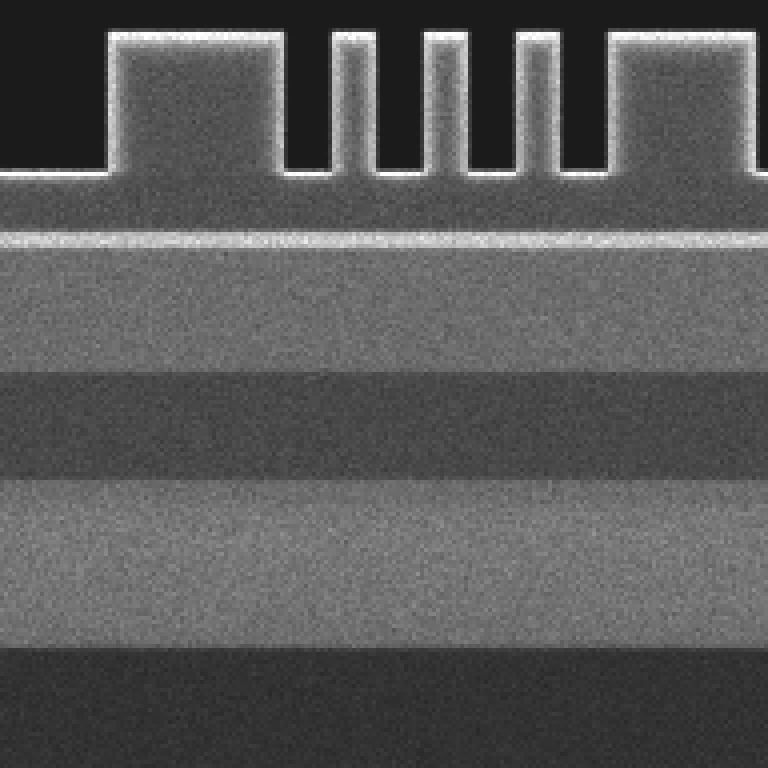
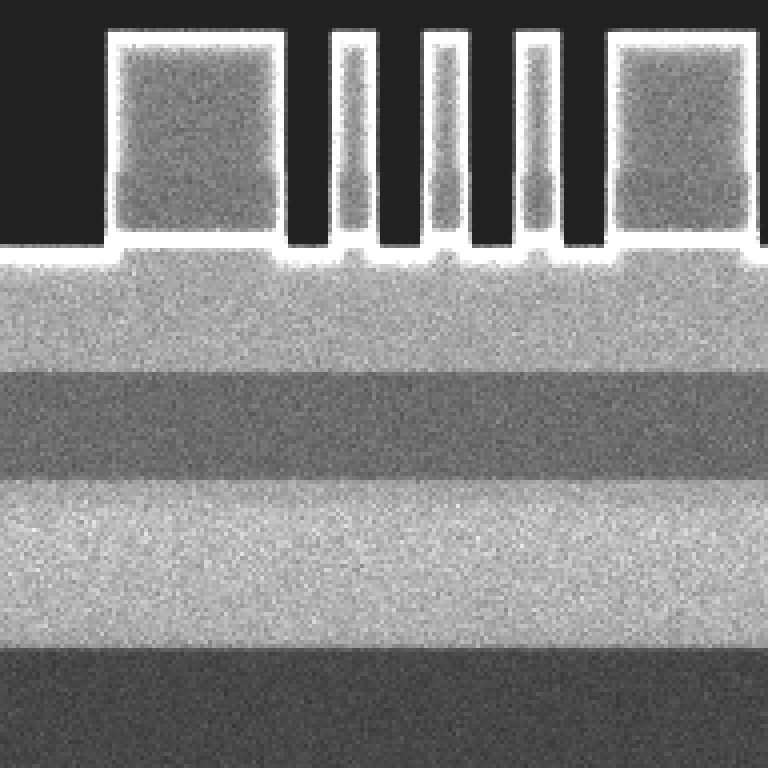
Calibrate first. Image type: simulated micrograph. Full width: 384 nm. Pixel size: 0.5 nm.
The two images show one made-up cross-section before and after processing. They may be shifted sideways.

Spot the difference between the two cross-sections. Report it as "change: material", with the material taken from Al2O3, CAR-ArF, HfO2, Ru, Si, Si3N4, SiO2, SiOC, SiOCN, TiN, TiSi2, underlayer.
removed: HfO2 and TiN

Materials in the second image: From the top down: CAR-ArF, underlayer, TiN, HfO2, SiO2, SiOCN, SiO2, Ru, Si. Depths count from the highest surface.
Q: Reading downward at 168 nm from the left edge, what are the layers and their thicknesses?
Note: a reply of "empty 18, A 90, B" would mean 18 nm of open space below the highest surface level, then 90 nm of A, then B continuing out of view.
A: CAR-ArF 32, underlayer 38, TiN 30, HfO2 8, SiO2 62, SiOCN 54, SiO2 12, Ru 72, Si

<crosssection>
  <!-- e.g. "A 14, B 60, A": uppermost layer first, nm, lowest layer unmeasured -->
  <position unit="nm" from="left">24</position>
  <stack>empty 108, SiO2 62, SiOCN 54, SiO2 12, Ru 72, Si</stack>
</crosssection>